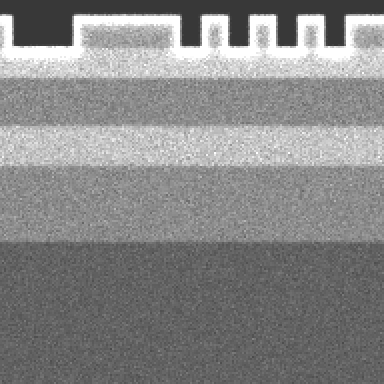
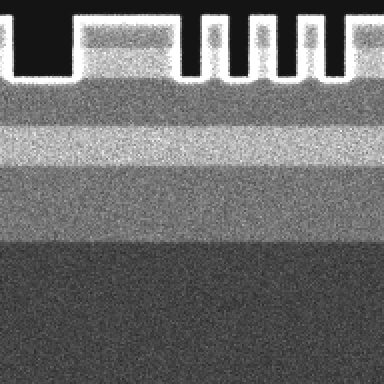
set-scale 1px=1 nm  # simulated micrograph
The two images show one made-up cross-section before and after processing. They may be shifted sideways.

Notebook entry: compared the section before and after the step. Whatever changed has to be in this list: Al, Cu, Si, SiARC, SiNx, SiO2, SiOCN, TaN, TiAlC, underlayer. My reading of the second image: SiO2 removed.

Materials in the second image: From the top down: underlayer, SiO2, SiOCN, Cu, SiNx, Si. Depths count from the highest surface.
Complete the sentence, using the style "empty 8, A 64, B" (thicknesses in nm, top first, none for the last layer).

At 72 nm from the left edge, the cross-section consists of empty 62, SiOCN 48, Cu 40, SiNx 76, Si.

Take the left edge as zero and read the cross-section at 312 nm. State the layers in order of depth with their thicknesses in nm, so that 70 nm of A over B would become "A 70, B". underlayer 32, SiO2 30, SiOCN 48, Cu 40, SiNx 76, Si